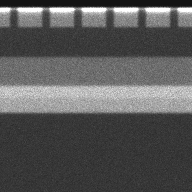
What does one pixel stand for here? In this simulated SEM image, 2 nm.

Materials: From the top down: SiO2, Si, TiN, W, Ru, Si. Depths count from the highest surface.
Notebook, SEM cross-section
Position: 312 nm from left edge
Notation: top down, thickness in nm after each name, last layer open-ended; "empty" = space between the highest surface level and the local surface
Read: SiO2 38, Si 60, TiN 58, W 24, Ru 30, Si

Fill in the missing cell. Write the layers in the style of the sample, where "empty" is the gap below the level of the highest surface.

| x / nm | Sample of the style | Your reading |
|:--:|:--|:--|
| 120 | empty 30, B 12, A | SiO2 38, Si 60, TiN 58, W 24, Ru 30, Si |